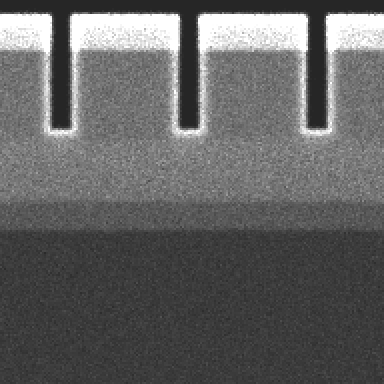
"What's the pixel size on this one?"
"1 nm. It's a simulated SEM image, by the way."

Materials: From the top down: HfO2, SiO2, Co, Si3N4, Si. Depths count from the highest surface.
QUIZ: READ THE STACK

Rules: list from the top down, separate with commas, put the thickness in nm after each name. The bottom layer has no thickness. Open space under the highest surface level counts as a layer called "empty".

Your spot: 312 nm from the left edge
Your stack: empty 114, SiO2 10, Co 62, Si3N4 28, Si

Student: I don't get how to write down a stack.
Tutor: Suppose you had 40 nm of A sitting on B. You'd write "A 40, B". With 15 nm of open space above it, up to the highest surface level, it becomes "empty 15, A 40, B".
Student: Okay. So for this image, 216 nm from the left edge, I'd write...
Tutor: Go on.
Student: HfO2 34, SiO2 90, Co 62, Si3N4 28, Si